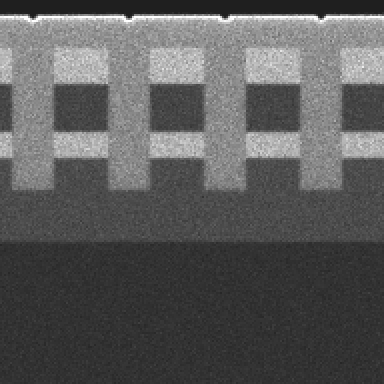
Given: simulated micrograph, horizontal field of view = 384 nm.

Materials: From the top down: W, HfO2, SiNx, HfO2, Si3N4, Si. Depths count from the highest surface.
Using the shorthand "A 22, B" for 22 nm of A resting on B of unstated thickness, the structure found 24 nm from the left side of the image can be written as W 174, Si3N4 52, Si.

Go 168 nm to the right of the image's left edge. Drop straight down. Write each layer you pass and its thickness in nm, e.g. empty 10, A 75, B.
W 32, HfO2 36, SiNx 48, HfO2 26, Si3N4 84, Si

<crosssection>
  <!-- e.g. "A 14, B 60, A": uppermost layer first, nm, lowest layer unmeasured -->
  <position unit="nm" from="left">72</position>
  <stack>W 32, HfO2 36, SiNx 48, HfO2 26, Si3N4 84, Si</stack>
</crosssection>